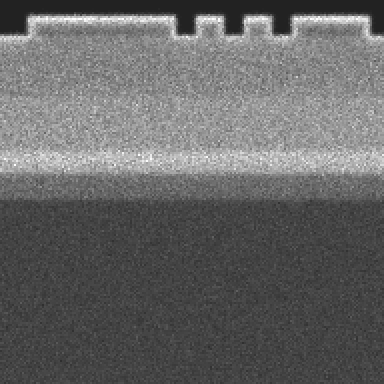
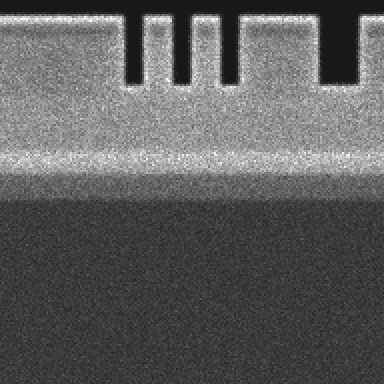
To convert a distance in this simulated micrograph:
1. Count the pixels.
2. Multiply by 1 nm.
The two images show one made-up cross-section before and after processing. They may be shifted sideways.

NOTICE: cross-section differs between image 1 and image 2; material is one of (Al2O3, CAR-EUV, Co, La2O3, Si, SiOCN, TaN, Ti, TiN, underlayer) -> removed: TiN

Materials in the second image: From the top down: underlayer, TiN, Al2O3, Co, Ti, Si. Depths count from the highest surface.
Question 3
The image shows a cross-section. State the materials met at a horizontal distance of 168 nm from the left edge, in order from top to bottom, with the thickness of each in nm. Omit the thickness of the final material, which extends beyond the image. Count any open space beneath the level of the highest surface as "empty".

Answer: underlayer 20, TiN 62, Al2O3 54, Co 22, Ti 26, Si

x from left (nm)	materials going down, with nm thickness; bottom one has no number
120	underlayer 20, TiN 62, Al2O3 54, Co 22, Ti 26, Si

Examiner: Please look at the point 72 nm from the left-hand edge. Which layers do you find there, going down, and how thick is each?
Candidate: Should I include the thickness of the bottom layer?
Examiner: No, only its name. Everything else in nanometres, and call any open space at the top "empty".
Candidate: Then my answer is underlayer 20, TiN 62, Al2O3 54, Co 22, Ti 26, Si